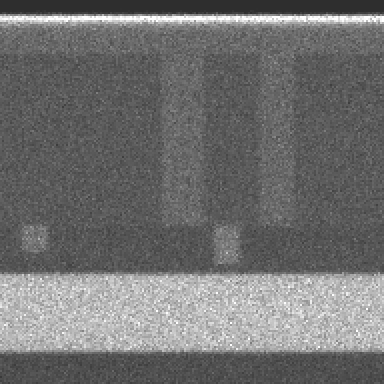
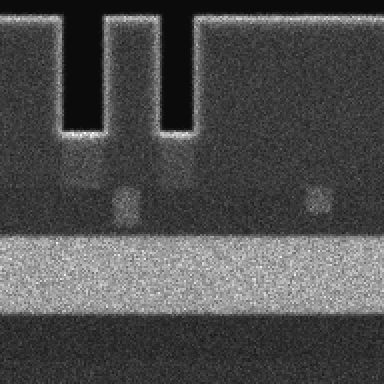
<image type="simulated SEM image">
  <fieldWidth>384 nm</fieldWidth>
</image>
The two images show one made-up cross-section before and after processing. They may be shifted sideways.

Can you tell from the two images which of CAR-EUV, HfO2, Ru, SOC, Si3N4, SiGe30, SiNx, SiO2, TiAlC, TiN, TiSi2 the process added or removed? Yes, it removed SiO2.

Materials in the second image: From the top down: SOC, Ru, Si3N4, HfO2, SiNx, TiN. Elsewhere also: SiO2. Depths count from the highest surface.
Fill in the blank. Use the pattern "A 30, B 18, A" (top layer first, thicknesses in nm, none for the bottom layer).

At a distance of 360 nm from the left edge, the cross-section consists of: SOC 172, Si3N4 48, HfO2 78, SiNx 46, TiN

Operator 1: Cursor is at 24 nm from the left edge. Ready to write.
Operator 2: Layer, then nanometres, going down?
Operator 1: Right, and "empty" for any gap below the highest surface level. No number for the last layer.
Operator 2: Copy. SOC 172, Si3N4 48, HfO2 78, SiNx 46, TiN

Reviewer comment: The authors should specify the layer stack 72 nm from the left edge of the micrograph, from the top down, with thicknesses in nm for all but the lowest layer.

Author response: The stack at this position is empty 116, SiO2 56, Si3N4 48, HfO2 78, SiNx 46, TiN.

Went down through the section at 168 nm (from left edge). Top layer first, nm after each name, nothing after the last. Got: empty 116, SiO2 56, Si3N4 48, HfO2 78, SiNx 46, TiN